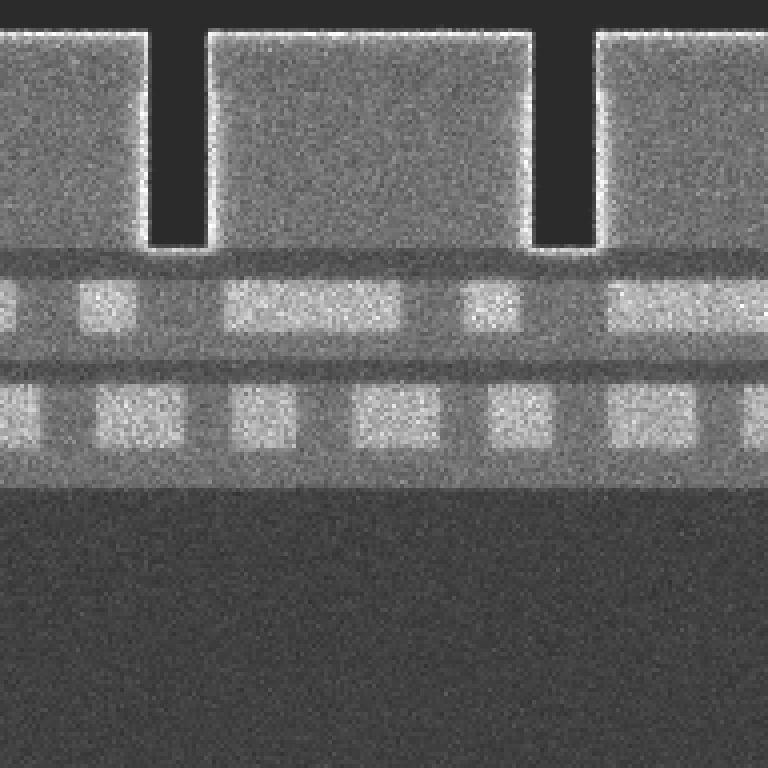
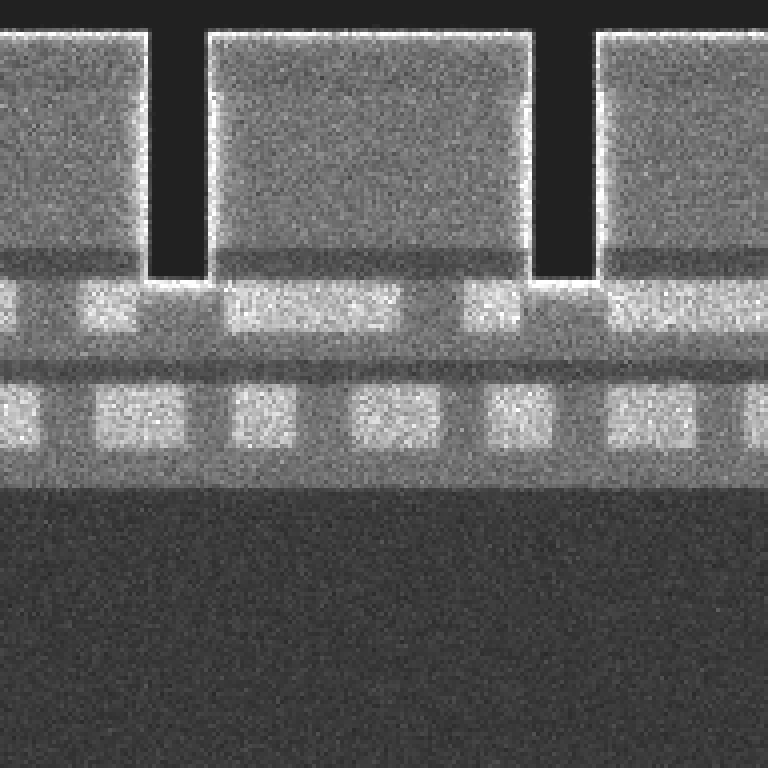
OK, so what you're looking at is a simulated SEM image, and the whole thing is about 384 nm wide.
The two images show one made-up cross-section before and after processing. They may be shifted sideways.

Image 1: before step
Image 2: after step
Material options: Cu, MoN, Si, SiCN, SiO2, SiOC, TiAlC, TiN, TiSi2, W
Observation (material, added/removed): SiCN, removed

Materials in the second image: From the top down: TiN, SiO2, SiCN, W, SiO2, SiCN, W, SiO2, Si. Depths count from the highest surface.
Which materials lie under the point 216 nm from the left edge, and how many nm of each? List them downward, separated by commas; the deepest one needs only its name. TiN 30, SiO2 78, SiCN 16, SiO2 40, SiCN 12, W 32, SiO2 20, Si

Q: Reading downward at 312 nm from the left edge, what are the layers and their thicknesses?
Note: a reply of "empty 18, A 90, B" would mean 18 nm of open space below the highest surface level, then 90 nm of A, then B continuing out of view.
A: TiN 30, SiO2 78, SiCN 16, W 26, SiO2 14, SiCN 12, W 32, SiO2 20, Si